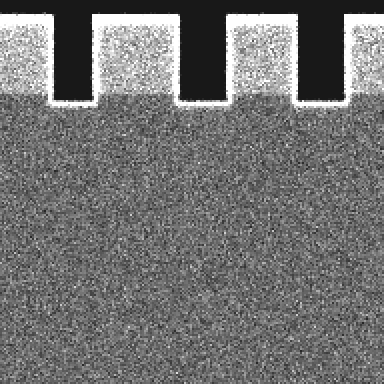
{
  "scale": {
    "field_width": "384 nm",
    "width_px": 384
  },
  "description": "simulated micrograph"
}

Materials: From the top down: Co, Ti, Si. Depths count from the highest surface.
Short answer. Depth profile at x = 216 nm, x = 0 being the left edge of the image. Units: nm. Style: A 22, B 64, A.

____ empty 86, Si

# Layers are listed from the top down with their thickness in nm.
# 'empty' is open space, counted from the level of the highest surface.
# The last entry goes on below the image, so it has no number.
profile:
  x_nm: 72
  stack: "empty 86, Si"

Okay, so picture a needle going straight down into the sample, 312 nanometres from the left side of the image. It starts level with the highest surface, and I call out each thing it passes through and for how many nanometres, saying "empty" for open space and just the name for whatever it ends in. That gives empty 86, Si